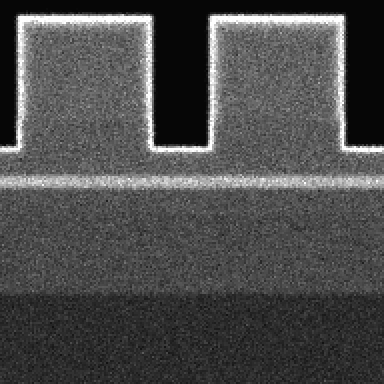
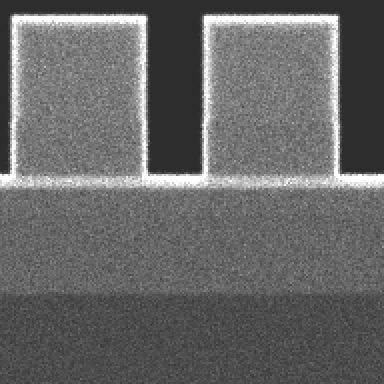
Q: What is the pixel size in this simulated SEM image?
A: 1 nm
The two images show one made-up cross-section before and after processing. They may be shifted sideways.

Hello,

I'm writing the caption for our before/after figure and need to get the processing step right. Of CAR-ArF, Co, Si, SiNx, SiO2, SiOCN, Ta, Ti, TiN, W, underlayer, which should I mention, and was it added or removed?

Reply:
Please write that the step removed TiN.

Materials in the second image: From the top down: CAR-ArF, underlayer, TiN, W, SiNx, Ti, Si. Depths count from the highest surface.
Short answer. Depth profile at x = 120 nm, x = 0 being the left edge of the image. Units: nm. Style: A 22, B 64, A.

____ CAR-ArF 76, underlayer 28, TiN 56, W 12, SiNx 26, Ti 80, Si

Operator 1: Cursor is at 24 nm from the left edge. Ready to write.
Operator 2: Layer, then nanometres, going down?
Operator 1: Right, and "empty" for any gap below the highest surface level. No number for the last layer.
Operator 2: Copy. CAR-ArF 76, underlayer 28, TiN 56, W 12, SiNx 26, Ti 80, Si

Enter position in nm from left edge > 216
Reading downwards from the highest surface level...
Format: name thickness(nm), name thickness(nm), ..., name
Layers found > CAR-ArF 76, underlayer 28, TiN 56, W 12, SiNx 26, Ti 80, Si